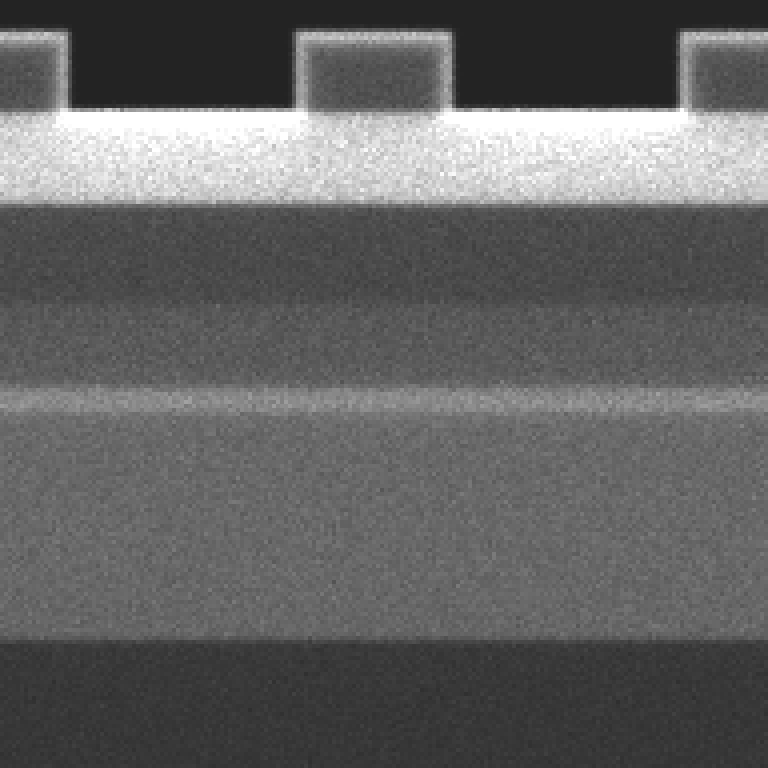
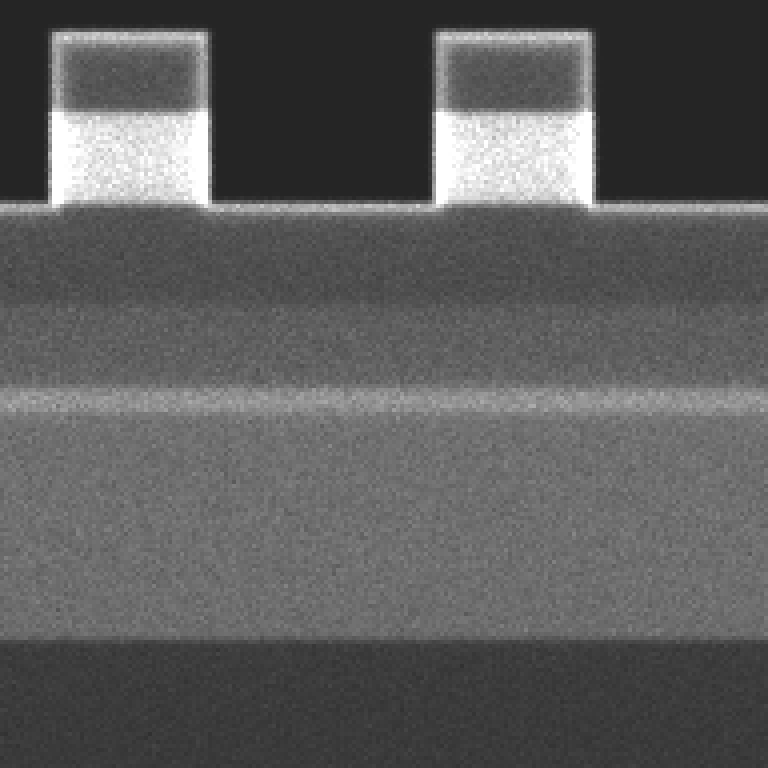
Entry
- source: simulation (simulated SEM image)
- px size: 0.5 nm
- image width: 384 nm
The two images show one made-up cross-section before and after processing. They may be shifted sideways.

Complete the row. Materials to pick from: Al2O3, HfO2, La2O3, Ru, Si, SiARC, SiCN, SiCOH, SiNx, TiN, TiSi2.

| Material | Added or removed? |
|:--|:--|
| HfO2 | removed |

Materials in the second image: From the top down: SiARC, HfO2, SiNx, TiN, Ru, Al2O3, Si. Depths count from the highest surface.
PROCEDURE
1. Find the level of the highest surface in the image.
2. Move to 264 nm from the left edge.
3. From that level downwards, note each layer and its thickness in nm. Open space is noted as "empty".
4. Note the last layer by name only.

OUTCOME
SiARC 40, HfO2 46, SiNx 50, TiN 42, Ru 12, Al2O3 114, Si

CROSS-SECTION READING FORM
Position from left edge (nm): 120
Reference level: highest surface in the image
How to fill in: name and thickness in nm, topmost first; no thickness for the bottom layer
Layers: empty 86, SiNx 50, TiN 42, Ru 12, Al2O3 114, Si